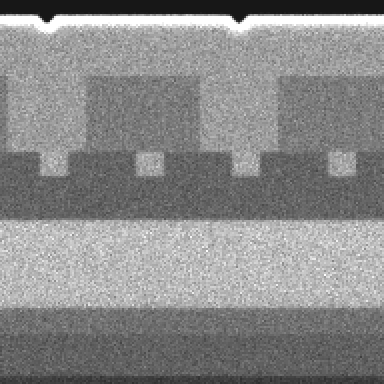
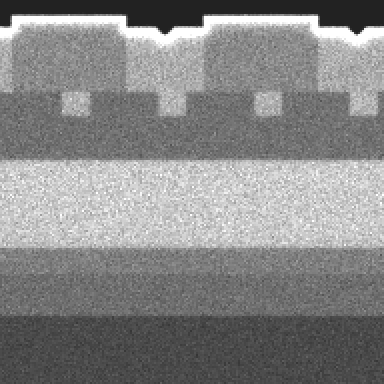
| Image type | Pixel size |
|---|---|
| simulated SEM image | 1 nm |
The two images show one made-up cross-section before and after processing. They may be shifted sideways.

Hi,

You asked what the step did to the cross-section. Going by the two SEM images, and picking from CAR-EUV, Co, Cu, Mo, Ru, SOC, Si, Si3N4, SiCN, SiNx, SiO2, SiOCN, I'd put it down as SiO2, removed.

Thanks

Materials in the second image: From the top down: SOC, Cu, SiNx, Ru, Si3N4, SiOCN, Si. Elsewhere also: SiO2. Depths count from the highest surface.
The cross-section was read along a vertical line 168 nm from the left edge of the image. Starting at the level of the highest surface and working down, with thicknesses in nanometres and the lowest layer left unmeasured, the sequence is empty 18, SiO2 58, Cu 24, SiNx 44, Ru 88, Si3N4 26, SiOCN 42, Si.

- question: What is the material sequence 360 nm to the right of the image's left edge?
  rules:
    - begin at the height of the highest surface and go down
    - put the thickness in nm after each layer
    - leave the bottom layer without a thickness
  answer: empty 18, SiO2 58, Cu 24, SiNx 44, Ru 88, Si3N4 26, SiOCN 42, Si